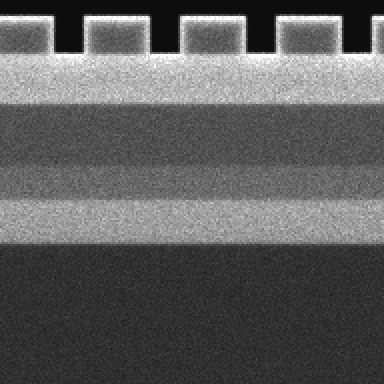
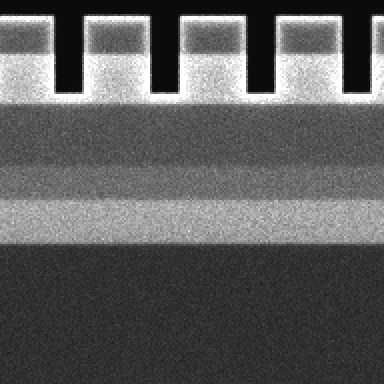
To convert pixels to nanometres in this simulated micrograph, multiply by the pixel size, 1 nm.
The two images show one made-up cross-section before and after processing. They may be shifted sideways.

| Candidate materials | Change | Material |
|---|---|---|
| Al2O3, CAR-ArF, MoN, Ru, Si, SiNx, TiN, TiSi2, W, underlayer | removed | W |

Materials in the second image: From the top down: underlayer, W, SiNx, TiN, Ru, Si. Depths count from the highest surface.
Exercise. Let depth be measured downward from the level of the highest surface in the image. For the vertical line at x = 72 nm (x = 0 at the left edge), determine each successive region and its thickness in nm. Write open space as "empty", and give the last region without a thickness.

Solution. empty 78, W 10, SiNx 62, TiN 34, Ru 44, Si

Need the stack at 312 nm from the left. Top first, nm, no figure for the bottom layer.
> underlayer 38, W 50, SiNx 62, TiN 34, Ru 44, Si